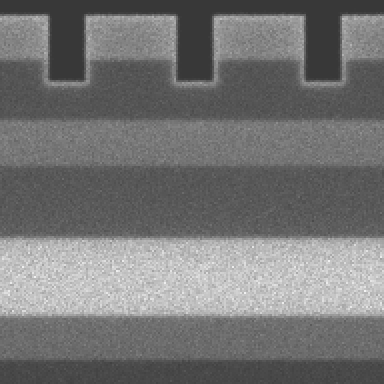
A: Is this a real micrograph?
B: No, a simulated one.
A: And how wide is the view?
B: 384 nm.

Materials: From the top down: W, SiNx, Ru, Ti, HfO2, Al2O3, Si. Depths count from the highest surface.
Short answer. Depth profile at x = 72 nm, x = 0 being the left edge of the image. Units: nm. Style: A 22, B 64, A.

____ empty 66, SiNx 38, Ru 46, Ti 72, HfO2 78, Al2O3 44, Si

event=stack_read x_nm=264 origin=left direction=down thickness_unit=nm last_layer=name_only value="W 44, SiNx 60, Ru 46, Ti 72, HfO2 78, Al2O3 44, Si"